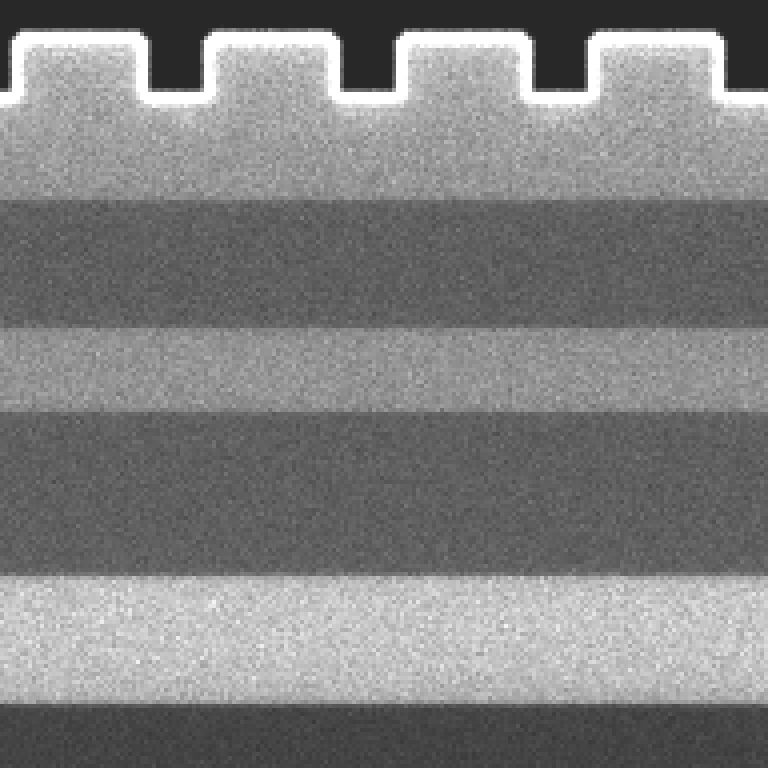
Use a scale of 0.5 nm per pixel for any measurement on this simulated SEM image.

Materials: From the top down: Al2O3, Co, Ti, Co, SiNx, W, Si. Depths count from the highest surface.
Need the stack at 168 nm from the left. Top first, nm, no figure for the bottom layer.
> empty 4, Al2O3 36, Co 44, Ti 64, Co 42, SiNx 82, W 64, Si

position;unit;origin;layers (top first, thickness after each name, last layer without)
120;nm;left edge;Al2O3 10, Co 74, Ti 64, Co 42, SiNx 82, W 64, Si